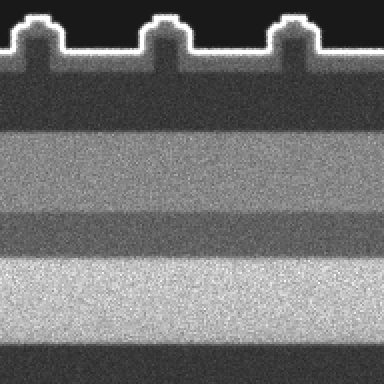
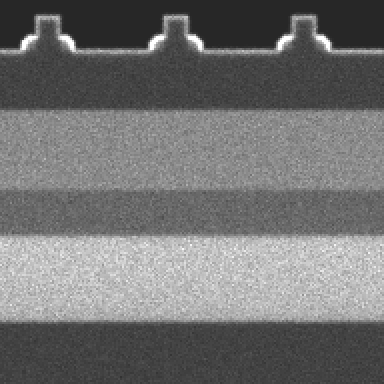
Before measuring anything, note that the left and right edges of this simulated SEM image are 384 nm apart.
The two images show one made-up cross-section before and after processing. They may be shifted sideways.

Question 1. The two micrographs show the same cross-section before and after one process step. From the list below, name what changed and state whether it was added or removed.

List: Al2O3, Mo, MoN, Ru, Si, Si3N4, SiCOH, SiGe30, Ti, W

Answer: Si3N4, removed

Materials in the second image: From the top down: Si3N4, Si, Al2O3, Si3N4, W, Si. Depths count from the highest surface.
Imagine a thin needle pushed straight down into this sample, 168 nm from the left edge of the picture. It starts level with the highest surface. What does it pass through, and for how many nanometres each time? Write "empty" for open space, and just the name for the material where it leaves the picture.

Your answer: Si 94, Al2O3 80, Si3N4 46, W 86, Si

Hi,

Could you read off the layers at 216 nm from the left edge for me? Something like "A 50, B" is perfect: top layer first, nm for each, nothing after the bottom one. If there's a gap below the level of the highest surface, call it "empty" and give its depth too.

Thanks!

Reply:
empty 34, Si 60, Al2O3 80, Si3N4 46, W 86, Si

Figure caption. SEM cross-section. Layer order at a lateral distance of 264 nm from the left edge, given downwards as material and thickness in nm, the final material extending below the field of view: empty 34, Si 60, Al2O3 80, Si3N4 46, W 86, Si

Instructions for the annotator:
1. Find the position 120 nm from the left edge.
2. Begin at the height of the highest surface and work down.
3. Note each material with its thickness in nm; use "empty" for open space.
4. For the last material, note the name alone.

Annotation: empty 34, Si 60, Al2O3 80, Si3N4 46, W 86, Si